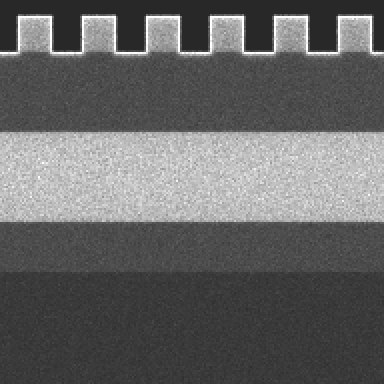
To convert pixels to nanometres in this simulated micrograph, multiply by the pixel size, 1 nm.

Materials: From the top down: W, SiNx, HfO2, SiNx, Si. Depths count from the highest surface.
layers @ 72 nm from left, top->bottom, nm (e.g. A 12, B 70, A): empty 36, SiNx 80, HfO2 90, SiNx 50, Si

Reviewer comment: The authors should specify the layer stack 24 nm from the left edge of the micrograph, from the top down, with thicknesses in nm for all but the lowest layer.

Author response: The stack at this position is W 36, SiNx 80, HfO2 90, SiNx 50, Si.